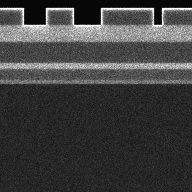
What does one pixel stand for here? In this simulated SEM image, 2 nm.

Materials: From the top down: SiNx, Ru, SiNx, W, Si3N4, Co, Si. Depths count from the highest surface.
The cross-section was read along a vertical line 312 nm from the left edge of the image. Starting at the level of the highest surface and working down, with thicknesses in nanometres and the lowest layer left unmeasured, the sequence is empty 34, Ru 34, SiNx 42, W 12, Si3N4 22, Co 8, Si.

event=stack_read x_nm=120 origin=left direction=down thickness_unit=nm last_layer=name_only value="SiNx 34, Ru 34, SiNx 42, W 12, Si3N4 22, Co 8, Si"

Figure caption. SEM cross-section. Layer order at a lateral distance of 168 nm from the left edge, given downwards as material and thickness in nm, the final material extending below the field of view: empty 34, Ru 34, SiNx 42, W 12, Si3N4 22, Co 8, Si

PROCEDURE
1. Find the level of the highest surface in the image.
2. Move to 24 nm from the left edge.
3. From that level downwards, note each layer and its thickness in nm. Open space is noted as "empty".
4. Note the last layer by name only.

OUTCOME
SiNx 34, Ru 34, SiNx 42, W 12, Si3N4 22, Co 8, Si